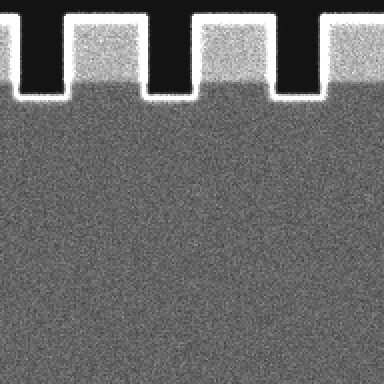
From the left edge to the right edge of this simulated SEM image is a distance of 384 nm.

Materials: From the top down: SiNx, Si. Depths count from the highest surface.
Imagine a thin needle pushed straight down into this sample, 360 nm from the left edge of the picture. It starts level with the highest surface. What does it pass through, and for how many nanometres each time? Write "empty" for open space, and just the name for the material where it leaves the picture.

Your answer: SiNx 66, Si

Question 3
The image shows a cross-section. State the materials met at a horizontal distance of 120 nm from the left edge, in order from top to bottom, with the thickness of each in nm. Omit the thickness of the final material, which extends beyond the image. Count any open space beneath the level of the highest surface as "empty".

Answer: SiNx 66, Si